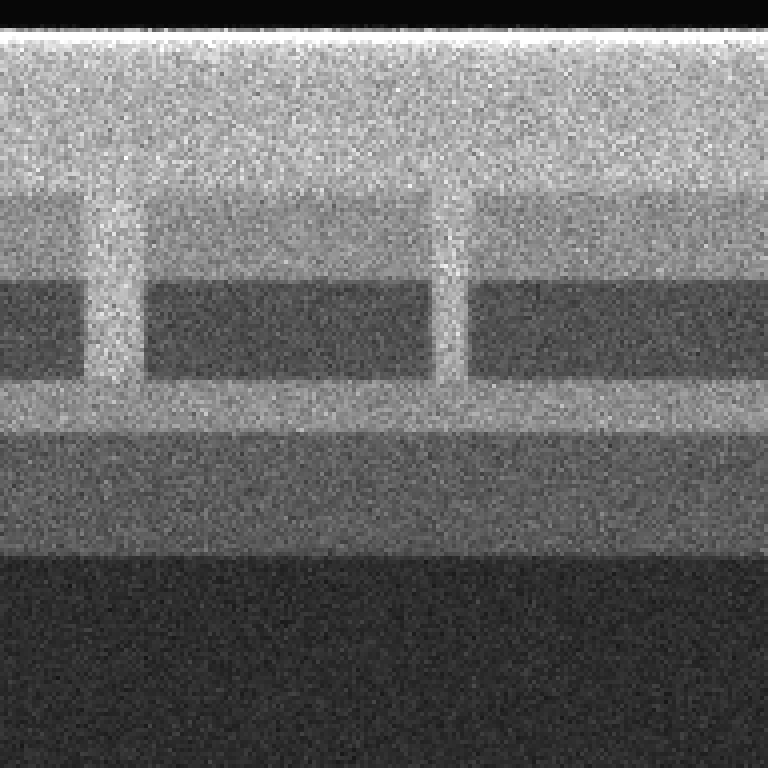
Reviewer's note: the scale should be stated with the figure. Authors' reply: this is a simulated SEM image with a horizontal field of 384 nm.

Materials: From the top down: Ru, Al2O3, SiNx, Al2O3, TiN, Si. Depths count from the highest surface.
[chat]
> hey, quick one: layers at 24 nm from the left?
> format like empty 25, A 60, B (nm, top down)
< Ru 80, Al2O3 44, SiNx 50, Al2O3 26, TiN 62, Si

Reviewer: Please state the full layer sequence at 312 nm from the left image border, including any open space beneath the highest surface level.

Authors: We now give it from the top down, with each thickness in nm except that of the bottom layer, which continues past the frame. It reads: Ru 80, Al2O3 44, SiNx 50, Al2O3 26, TiN 62, Si